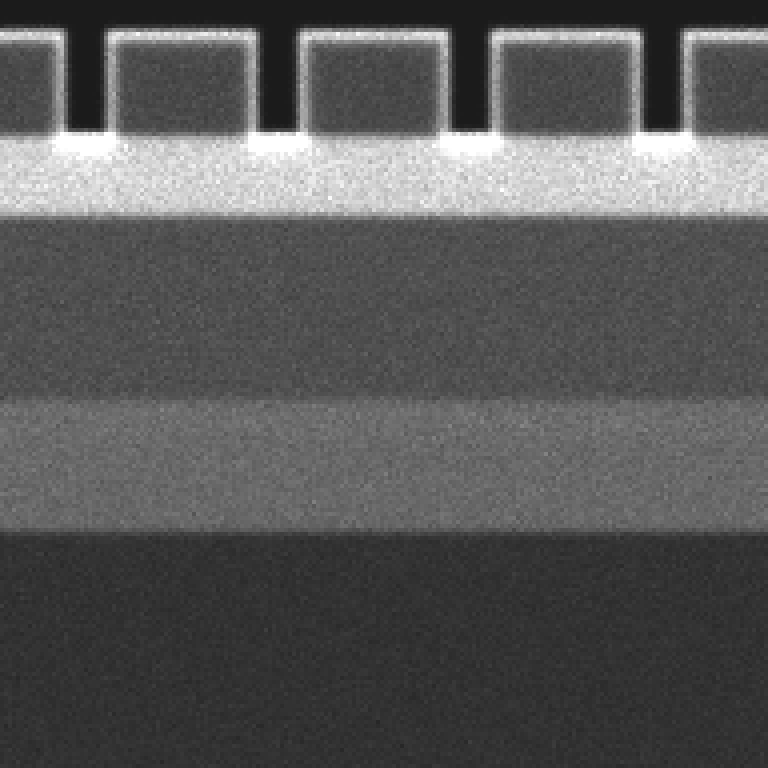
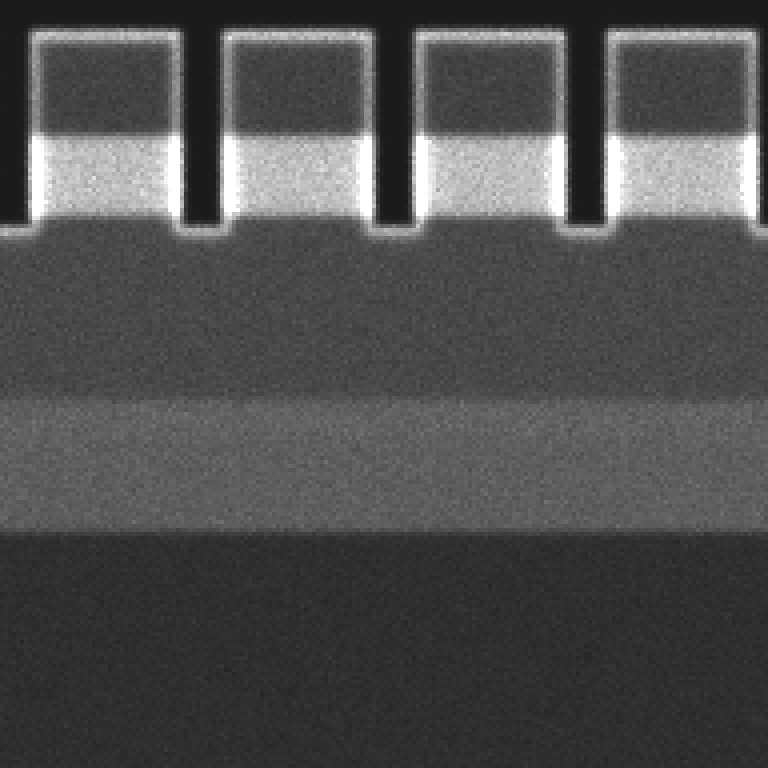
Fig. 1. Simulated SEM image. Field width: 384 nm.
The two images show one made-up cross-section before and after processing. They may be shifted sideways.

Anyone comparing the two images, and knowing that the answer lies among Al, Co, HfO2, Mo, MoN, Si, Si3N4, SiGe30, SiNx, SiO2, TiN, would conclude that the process removed HfO2 and Si3N4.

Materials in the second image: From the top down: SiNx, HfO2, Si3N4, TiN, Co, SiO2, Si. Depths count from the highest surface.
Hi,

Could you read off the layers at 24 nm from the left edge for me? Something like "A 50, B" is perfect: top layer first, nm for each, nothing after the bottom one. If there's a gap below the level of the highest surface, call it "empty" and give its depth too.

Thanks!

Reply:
SiNx 52, HfO2 40, Si3N4 36, TiN 56, Co 18, SiO2 48, Si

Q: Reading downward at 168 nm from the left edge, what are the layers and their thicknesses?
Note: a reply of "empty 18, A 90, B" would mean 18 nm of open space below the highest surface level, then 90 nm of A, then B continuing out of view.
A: SiNx 52, HfO2 40, Si3N4 36, TiN 56, Co 18, SiO2 48, Si